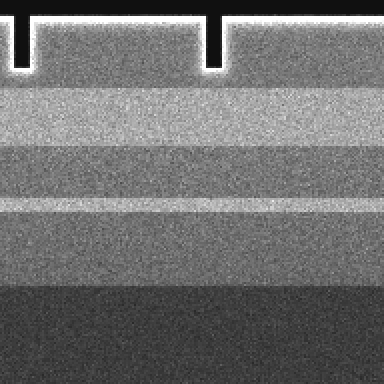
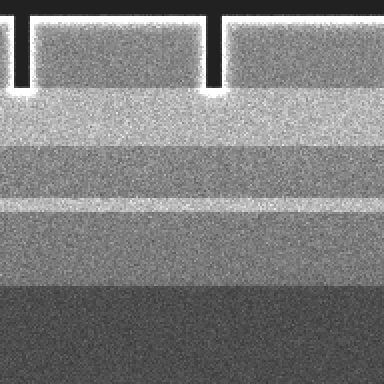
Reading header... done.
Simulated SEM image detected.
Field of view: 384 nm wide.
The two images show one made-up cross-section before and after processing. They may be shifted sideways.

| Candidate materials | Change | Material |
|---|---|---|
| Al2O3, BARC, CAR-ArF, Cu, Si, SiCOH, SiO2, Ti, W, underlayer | removed | underlayer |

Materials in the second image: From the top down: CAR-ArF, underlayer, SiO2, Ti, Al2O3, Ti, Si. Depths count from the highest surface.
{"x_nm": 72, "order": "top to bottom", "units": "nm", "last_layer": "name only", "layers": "CAR-ArF 52, underlayer 20, SiO2 58, Ti 52, Al2O3 14, Ti 74, Si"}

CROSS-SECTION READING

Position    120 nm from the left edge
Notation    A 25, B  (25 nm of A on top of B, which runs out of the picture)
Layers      CAR-ArF 52, underlayer 20, SiO2 58, Ti 52, Al2O3 14, Ti 74, Si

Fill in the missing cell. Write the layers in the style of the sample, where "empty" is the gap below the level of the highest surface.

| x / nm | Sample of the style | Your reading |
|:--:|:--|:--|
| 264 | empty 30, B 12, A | CAR-ArF 52, underlayer 20, SiO2 58, Ti 52, Al2O3 14, Ti 74, Si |